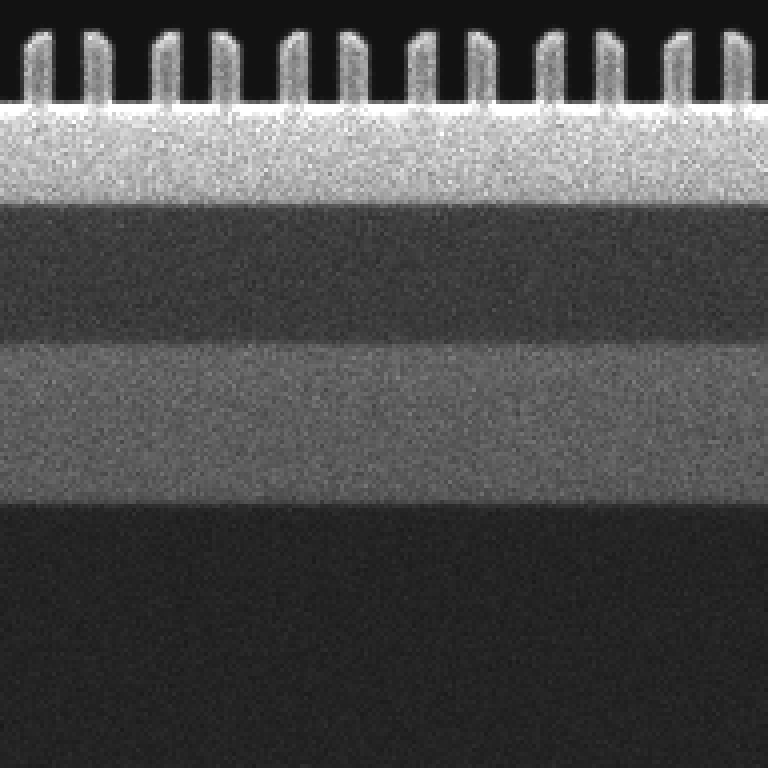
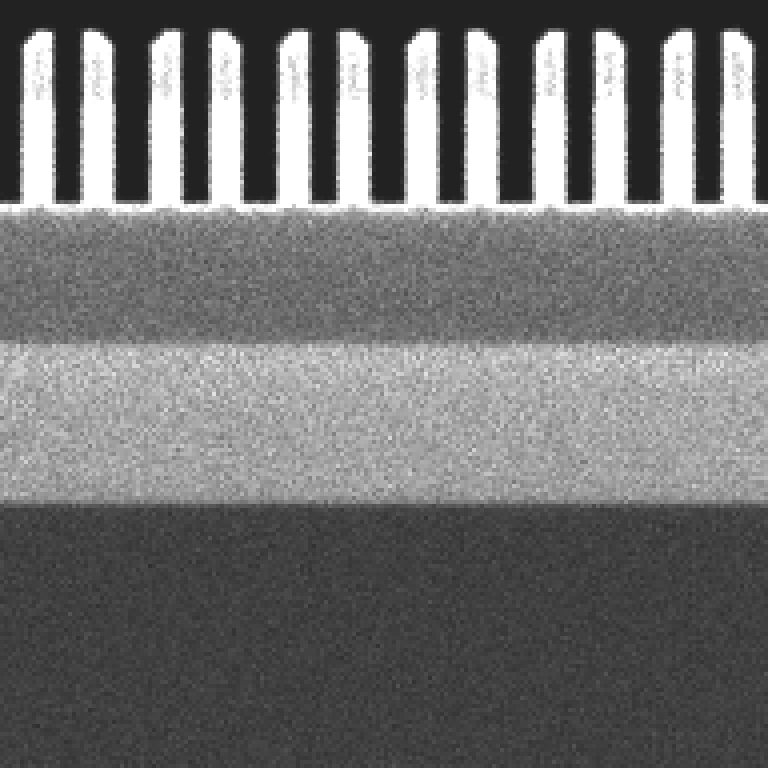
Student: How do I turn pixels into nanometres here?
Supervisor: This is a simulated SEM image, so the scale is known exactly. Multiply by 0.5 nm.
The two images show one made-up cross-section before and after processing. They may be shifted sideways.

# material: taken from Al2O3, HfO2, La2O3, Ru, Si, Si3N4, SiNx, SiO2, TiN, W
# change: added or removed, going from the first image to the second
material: HfO2
change: removed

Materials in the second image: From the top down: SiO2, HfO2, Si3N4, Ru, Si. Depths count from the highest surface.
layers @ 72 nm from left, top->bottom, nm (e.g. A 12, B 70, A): empty 86, Si3N4 70, Ru 80, Si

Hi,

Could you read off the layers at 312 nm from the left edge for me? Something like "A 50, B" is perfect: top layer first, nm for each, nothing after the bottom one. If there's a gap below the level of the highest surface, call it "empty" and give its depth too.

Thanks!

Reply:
empty 86, Si3N4 70, Ru 80, Si